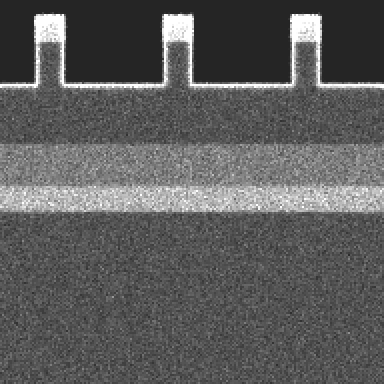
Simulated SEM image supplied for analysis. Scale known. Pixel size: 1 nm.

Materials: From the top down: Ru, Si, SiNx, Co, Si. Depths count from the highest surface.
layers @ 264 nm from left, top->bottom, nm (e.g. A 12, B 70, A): empty 68, Si 60, SiNx 42, Co 26, Si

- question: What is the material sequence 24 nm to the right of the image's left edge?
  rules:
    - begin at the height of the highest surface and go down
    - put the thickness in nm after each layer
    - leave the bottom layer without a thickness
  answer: empty 68, Si 60, SiNx 42, Co 26, Si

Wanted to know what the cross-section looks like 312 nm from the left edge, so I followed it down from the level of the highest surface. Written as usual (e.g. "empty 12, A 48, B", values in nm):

Ru 26, Si 102, SiNx 42, Co 26, Si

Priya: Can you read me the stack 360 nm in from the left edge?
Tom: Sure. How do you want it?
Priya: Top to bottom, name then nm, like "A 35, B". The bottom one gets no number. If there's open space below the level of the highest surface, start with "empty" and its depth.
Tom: empty 68, Si 60, SiNx 42, Co 26, Si